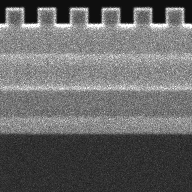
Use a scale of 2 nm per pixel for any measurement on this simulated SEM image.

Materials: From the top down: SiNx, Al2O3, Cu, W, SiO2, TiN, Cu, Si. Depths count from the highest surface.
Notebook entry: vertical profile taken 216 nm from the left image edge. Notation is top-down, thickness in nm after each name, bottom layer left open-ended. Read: SiNx 32, Al2O3 60, Cu 64, W 8, SiO2 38, TiN 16, Cu 34, Si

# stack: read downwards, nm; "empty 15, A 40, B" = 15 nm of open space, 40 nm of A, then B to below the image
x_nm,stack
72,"empty 32, Al2O3 60, Cu 64, W 8, SiO2 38, TiN 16, Cu 34, Si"